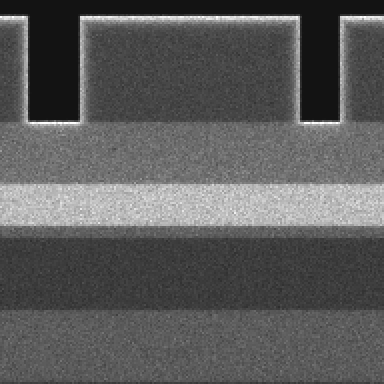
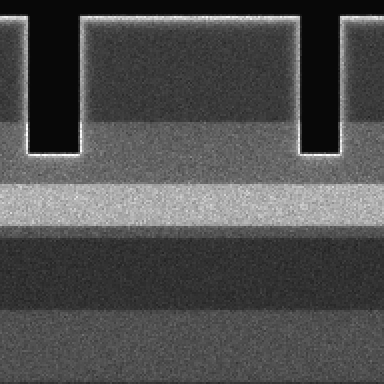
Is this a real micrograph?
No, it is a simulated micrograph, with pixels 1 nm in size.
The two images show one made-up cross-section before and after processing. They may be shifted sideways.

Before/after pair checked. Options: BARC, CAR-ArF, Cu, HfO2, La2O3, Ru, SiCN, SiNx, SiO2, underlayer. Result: removed Ru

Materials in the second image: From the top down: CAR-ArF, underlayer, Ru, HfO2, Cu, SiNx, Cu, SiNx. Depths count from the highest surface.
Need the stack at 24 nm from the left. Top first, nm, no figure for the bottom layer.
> CAR-ArF 62, underlayer 44, Ru 62, HfO2 42, Cu 12, SiNx 72, Cu 72, SiNx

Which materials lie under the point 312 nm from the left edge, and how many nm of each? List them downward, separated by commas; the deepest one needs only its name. empty 138, Ru 30, HfO2 42, Cu 12, SiNx 72, Cu 72, SiNx